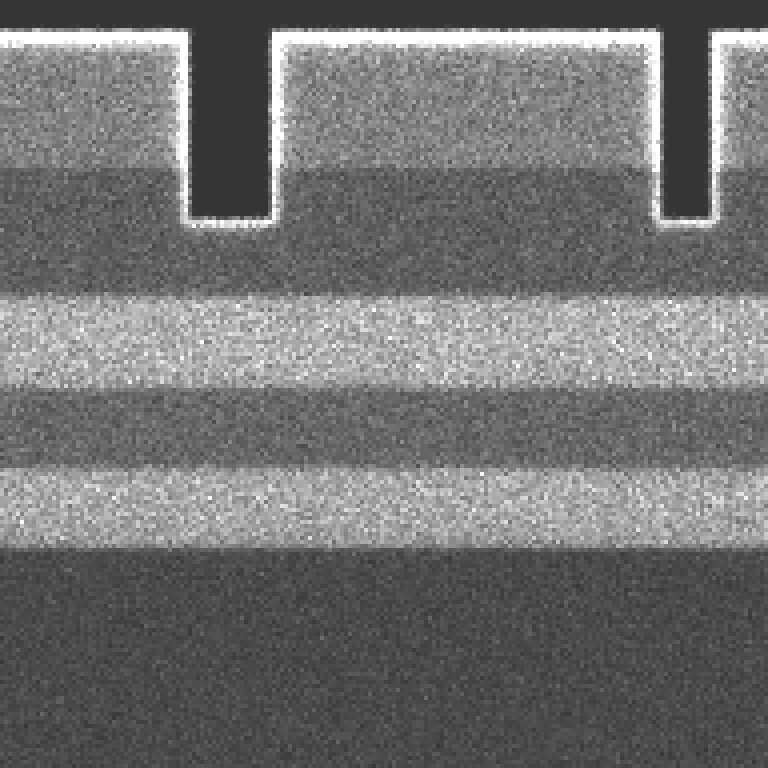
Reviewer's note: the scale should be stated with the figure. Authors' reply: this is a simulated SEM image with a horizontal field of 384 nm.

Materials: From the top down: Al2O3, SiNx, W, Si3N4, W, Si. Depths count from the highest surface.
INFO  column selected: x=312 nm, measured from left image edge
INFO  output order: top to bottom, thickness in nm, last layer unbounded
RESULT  Al2O3 68, SiNx 64, W 46, Si3N4 40, W 40, Si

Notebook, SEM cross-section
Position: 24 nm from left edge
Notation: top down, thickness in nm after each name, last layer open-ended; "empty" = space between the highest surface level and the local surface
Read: Al2O3 68, SiNx 64, W 46, Si3N4 40, W 40, Si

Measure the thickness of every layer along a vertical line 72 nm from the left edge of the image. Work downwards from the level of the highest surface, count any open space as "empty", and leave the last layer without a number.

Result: Al2O3 68, SiNx 64, W 46, Si3N4 40, W 40, Si